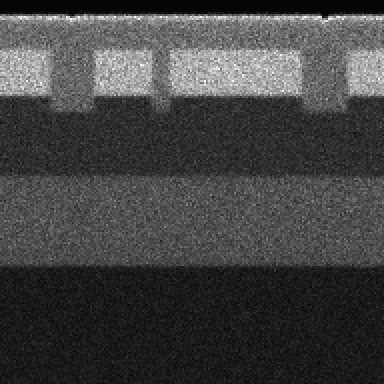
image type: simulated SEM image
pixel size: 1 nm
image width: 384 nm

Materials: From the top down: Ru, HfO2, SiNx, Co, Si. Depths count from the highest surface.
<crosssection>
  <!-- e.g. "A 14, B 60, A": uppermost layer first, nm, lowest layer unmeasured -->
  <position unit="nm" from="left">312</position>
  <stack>Ru 96, SiNx 64, Co 90, Si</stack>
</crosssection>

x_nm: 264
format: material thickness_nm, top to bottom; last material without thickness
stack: Ru 34, HfO2 46, SiNx 80, Co 90, Si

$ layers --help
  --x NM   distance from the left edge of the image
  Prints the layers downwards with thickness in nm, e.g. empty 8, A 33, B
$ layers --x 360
Ru 34, HfO2 46, SiNx 80, Co 90, Si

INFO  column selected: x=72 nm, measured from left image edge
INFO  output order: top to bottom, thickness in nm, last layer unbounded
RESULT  empty 2, Ru 94, SiNx 64, Co 90, Si